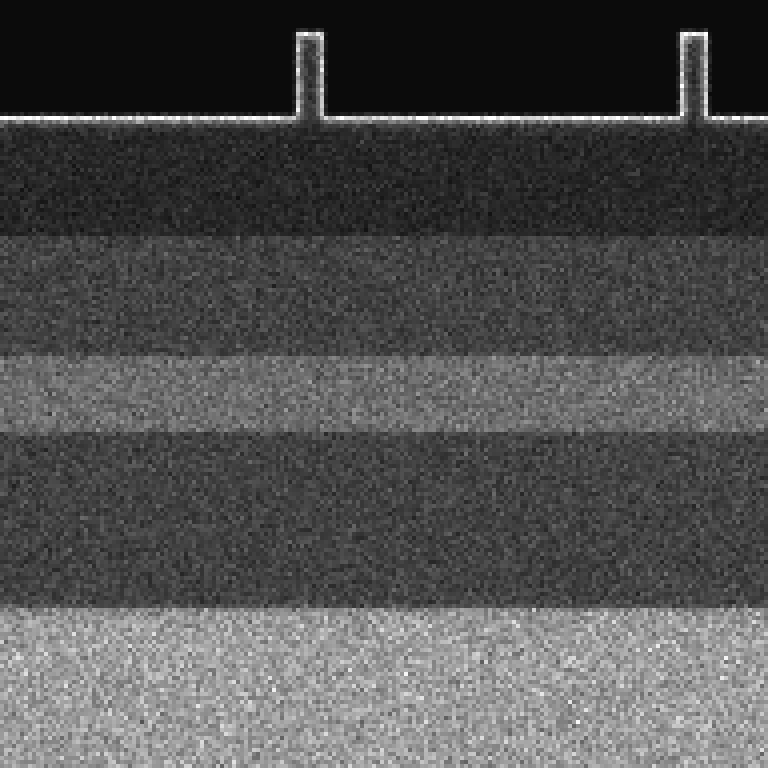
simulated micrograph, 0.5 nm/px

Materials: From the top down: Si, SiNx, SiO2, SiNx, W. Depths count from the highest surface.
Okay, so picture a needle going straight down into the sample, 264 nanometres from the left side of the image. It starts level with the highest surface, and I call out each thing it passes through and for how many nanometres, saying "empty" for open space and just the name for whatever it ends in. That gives empty 42, Si 60, SiNx 60, SiO2 38, SiNx 88, W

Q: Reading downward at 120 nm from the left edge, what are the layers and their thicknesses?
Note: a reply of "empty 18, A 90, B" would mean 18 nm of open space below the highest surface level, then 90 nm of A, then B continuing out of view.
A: empty 42, Si 60, SiNx 60, SiO2 38, SiNx 88, W